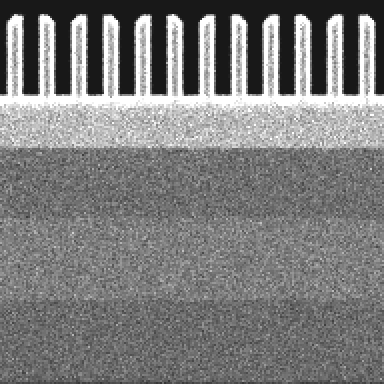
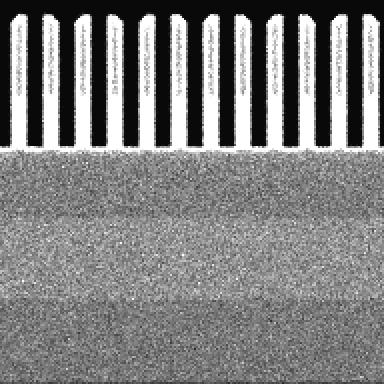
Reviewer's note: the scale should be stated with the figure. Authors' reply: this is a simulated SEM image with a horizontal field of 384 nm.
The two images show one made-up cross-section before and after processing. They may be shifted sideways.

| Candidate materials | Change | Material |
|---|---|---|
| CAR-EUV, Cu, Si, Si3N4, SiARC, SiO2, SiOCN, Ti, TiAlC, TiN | removed | SiO2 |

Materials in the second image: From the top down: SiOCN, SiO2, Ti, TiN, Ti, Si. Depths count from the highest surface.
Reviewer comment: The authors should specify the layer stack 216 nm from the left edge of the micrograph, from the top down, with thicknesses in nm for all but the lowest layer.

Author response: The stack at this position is SiOCN 80, SiO2 52, Ti 70, TiN 82, Ti 82, Si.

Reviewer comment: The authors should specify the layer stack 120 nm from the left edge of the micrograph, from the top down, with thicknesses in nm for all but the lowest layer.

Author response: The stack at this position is empty 6, SiOCN 74, SiO2 52, Ti 70, TiN 82, Ti 82, Si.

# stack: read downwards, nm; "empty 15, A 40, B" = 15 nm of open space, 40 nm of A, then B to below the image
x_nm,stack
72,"empty 132, Ti 70, TiN 82, Ti 82, Si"